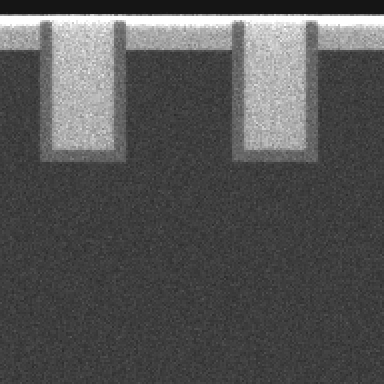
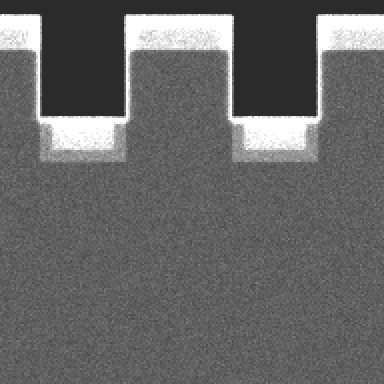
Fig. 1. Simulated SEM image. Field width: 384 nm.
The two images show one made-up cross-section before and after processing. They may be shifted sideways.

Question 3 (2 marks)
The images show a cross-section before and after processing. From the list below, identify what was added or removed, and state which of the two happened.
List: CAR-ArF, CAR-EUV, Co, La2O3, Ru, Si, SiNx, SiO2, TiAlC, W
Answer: Ru and SiNx was removed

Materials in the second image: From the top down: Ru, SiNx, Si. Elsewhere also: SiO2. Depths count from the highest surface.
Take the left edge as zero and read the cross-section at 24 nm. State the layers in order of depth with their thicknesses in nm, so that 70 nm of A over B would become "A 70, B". SiO2 34, Si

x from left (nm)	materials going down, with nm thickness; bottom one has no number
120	empty 102, SiNx 44, Si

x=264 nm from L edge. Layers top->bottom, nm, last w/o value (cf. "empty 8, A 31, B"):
empty 102, Ru 32, SiNx 12, Si